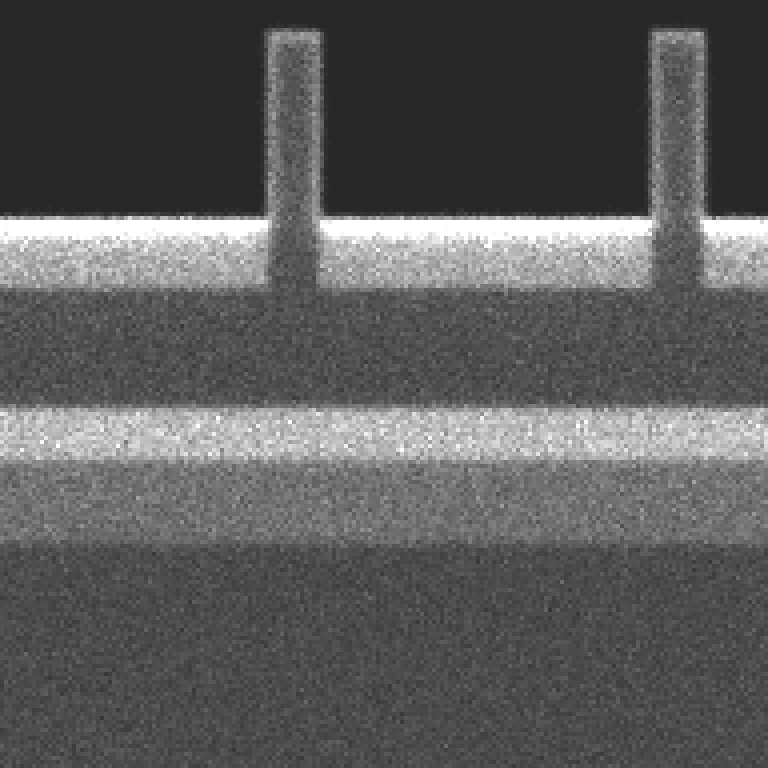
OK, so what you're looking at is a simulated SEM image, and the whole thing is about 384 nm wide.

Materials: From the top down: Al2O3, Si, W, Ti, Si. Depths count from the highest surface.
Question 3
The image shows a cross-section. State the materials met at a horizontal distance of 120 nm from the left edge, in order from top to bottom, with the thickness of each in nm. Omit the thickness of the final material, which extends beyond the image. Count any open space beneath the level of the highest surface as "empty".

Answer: empty 94, Al2O3 34, Si 60, W 26, Ti 42, Si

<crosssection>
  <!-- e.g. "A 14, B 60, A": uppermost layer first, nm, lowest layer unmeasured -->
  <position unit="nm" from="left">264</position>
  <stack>empty 94, Al2O3 34, Si 60, W 26, Ti 42, Si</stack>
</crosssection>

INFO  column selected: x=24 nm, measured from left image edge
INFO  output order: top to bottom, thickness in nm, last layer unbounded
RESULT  empty 94, Al2O3 34, Si 60, W 26, Ti 42, Si